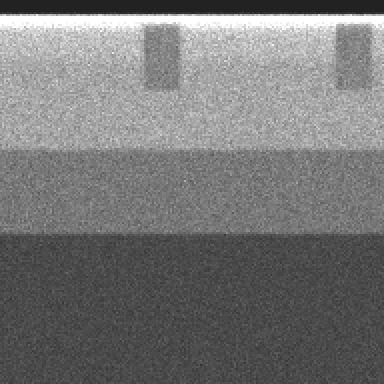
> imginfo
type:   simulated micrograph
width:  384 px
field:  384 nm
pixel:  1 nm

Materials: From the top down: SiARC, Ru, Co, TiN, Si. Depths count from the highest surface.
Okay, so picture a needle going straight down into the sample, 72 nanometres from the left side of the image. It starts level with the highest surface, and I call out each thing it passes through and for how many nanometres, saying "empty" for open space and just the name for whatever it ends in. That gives SiARC 8, Ru 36, Co 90, TiN 84, Si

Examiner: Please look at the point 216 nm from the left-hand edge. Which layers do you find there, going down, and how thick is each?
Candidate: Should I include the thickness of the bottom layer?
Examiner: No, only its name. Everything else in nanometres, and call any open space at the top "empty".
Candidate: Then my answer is SiARC 8, Ru 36, Co 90, TiN 84, Si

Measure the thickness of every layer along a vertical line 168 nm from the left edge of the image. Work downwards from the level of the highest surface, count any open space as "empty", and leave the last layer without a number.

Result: SiARC 74, Co 60, TiN 84, Si